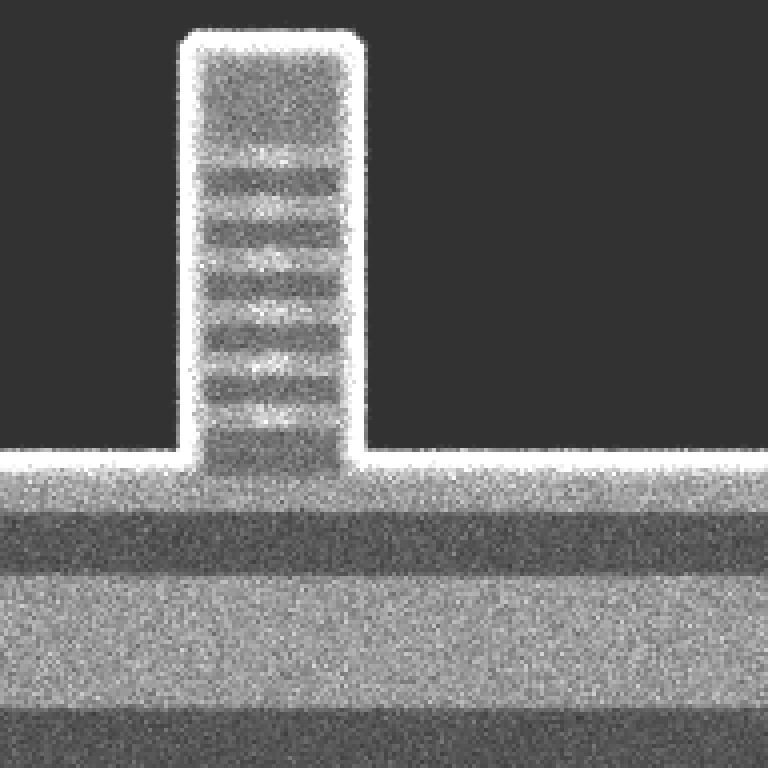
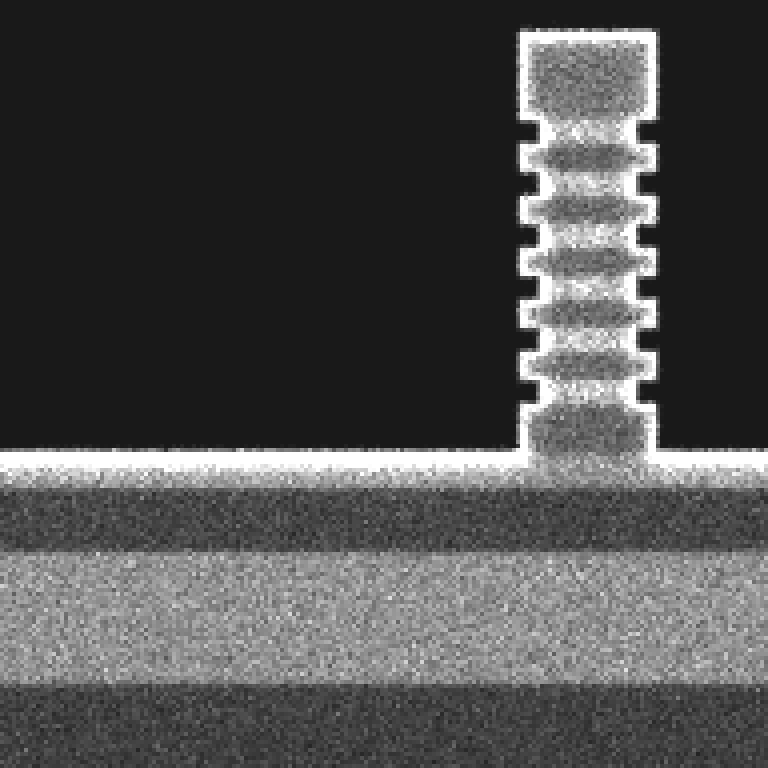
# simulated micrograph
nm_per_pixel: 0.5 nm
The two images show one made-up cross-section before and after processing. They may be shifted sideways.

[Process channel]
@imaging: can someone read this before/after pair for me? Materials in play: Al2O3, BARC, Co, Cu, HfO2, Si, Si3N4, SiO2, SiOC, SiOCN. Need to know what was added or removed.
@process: Al2O3 removed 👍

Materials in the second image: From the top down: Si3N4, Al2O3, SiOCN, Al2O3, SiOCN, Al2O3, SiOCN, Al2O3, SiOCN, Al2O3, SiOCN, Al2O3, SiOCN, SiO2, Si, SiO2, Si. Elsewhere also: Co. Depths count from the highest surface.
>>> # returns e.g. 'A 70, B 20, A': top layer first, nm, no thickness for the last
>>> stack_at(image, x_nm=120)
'empty 210, SiO2 18, Si 32, SiO2 66, Si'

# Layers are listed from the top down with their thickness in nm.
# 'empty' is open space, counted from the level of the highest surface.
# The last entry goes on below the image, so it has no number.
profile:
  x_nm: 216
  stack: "empty 210, SiO2 18, Si 32, SiO2 66, Si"